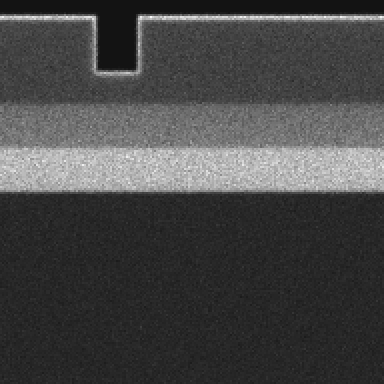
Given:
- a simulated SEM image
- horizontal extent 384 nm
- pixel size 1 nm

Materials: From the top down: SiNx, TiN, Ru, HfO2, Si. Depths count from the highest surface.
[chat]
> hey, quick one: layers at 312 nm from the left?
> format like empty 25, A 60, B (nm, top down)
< SiNx 10, TiN 78, Ru 44, HfO2 44, Si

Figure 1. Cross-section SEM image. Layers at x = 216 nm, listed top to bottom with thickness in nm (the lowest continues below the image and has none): SiNx 10, TiN 78, Ru 44, HfO2 44, Si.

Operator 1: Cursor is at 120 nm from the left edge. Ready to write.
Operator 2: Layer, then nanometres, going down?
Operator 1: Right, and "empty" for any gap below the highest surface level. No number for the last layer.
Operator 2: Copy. empty 56, TiN 32, Ru 44, HfO2 44, Si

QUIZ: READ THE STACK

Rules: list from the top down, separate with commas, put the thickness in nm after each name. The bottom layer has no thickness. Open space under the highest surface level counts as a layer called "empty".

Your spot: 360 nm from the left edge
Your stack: SiNx 10, TiN 78, Ru 44, HfO2 44, Si